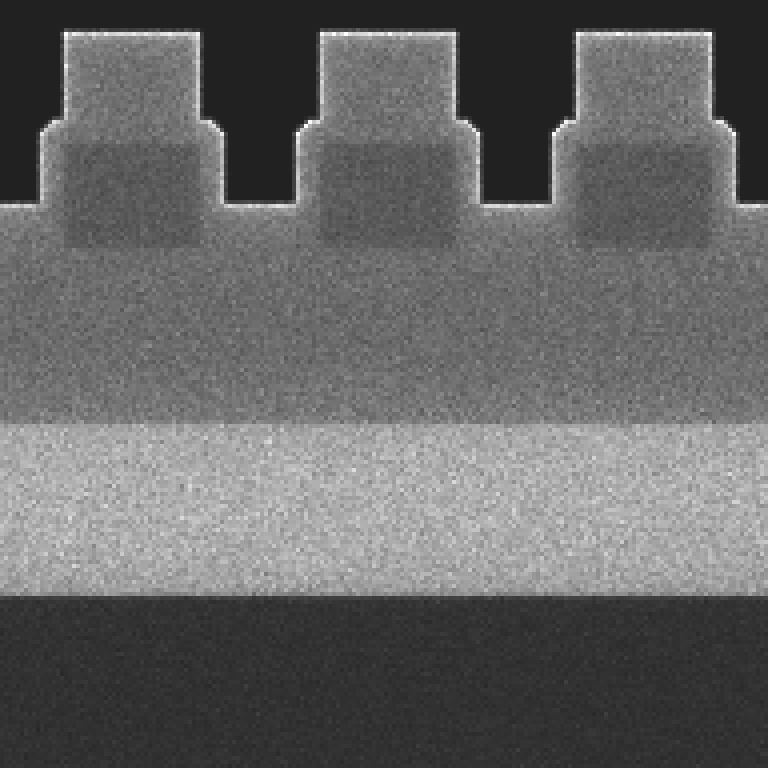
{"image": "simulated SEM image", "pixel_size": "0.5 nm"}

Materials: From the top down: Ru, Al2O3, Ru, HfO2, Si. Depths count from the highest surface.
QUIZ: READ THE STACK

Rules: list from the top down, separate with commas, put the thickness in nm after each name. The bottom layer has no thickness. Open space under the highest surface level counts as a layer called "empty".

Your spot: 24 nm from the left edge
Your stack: empty 46, Ru 150, HfO2 86, Si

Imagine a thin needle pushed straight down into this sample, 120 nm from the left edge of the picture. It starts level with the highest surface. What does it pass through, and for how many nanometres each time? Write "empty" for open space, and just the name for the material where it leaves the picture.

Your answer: empty 86, Ru 110, HfO2 86, Si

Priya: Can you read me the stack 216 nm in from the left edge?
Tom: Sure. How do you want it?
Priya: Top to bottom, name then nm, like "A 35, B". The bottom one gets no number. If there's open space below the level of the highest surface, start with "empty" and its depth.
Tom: Ru 56, Al2O3 52, Ru 88, HfO2 86, Si